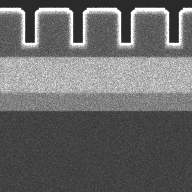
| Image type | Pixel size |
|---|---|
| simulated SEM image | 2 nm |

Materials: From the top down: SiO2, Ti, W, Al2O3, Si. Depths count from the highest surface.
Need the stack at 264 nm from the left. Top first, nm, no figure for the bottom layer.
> empty 6, SiO2 76, Ti 16, W 72, Al2O3 36, Si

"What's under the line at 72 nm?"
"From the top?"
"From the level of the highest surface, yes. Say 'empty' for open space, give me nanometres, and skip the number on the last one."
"empty 6, SiO2 76, Ti 16, W 72, Al2O3 36, Si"